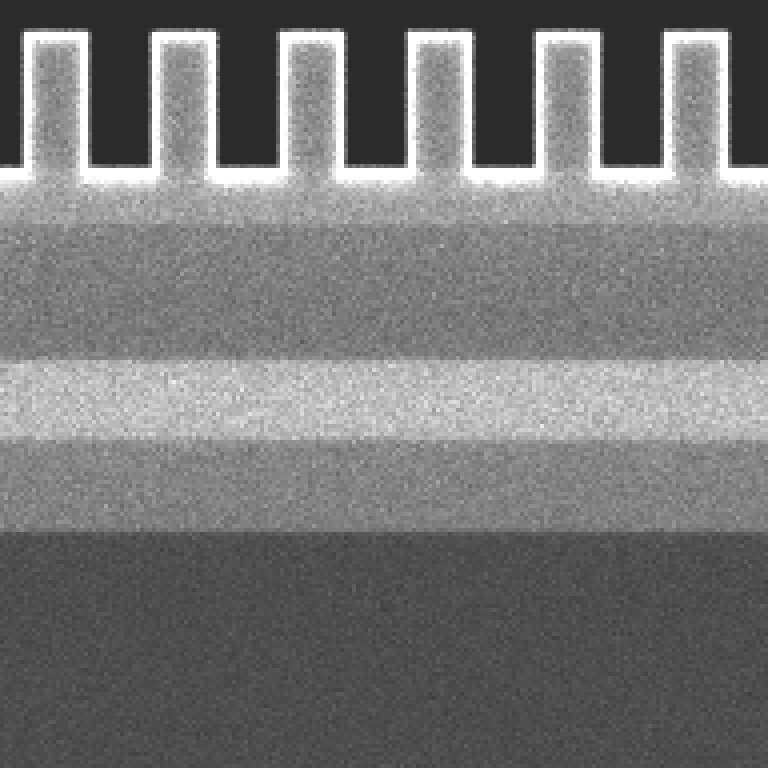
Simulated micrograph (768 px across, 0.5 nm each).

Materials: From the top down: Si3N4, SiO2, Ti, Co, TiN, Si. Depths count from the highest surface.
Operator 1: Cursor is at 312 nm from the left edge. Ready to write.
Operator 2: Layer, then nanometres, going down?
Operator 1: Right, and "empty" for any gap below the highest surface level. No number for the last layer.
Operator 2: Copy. empty 68, SiO2 28, Ti 68, Co 40, TiN 46, Si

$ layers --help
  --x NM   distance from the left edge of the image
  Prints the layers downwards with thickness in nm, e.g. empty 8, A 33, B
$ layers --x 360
Si3N4 68, SiO2 28, Ti 68, Co 40, TiN 46, Si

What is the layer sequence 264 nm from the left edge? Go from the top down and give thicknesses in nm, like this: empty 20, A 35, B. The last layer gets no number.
empty 68, SiO2 28, Ti 68, Co 40, TiN 46, Si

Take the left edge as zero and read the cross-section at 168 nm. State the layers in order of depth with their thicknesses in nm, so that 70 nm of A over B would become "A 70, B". Si3N4 68, SiO2 28, Ti 68, Co 40, TiN 46, Si